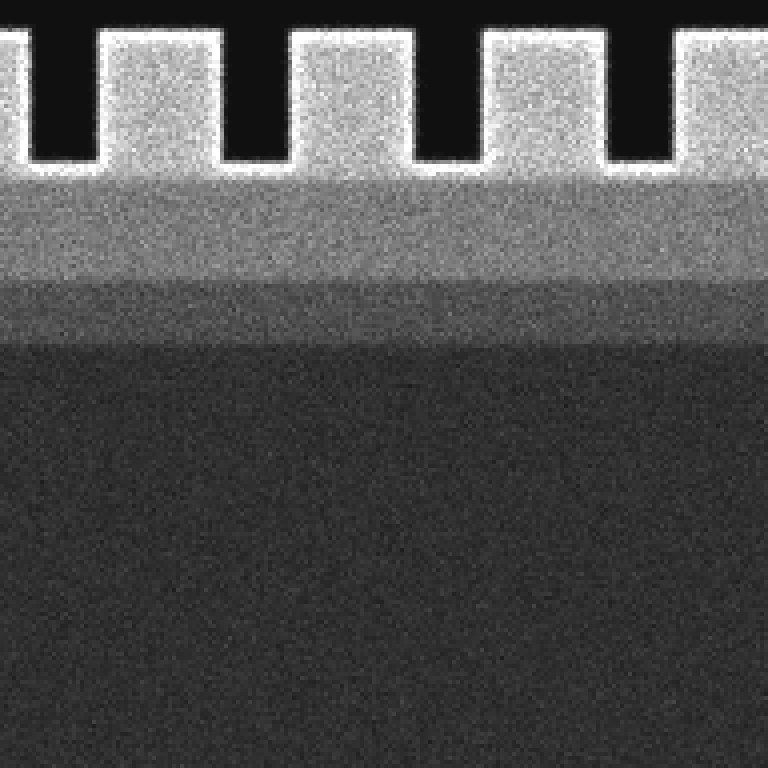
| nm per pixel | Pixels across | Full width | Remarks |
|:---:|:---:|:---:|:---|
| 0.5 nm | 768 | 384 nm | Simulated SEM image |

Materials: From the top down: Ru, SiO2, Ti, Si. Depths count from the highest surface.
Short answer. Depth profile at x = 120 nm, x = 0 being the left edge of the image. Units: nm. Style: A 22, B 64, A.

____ empty 66, Ru 8, SiO2 50, Ti 32, Si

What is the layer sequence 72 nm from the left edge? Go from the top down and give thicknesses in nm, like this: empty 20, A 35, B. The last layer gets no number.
Ru 74, SiO2 50, Ti 32, Si